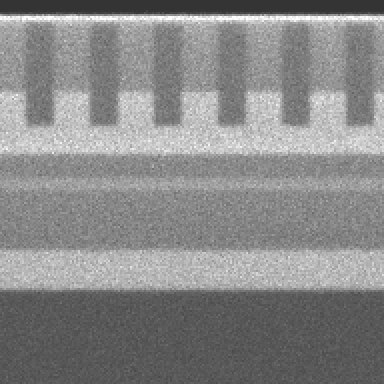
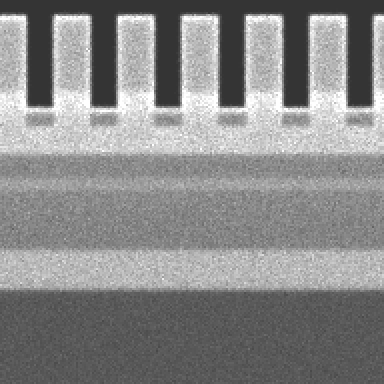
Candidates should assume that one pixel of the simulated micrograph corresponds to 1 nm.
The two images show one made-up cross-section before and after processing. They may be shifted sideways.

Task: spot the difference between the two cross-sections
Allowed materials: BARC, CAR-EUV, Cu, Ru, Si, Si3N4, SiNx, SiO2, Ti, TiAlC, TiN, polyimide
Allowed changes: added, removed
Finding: removed SiNx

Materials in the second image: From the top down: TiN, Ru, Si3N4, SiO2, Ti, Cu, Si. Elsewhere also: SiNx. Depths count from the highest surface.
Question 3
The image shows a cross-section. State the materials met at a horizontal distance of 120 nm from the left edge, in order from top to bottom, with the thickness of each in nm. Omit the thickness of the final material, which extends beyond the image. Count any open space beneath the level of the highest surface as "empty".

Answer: TiN 76, Ru 62, Si3N4 24, SiO2 12, Ti 60, Cu 40, Si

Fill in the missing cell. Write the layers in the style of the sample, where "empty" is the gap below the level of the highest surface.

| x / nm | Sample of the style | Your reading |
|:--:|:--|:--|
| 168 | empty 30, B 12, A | empty 92, SiNx 18, Ru 28, Si3N4 24, SiO2 12, Ti 60, Cu 40, Si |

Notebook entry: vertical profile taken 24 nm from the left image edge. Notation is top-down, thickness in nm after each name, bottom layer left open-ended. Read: TiN 76, Ru 62, Si3N4 24, SiO2 12, Ti 60, Cu 40, Si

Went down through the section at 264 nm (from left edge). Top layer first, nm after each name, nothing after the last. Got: TiN 76, Ru 62, Si3N4 24, SiO2 12, Ti 60, Cu 40, Si